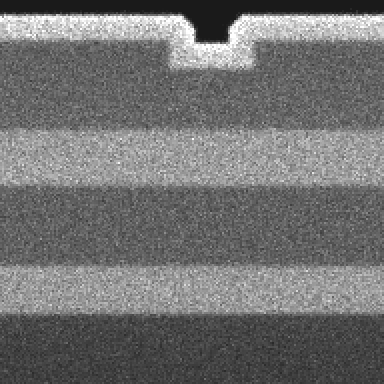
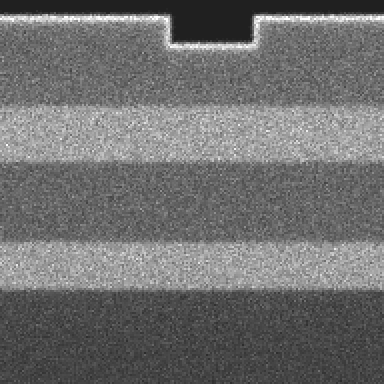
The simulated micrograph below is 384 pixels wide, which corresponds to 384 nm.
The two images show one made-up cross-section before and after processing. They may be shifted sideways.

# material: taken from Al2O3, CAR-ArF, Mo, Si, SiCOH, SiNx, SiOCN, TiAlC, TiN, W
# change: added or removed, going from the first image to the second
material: W
change: removed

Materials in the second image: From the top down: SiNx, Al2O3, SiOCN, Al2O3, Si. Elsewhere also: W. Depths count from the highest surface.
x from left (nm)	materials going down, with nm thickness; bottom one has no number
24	SiNx 90, Al2O3 56, SiOCN 80, Al2O3 48, Si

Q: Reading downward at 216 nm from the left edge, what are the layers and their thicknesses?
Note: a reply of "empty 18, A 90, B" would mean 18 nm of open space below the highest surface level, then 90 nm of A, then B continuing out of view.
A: empty 28, SiNx 62, Al2O3 56, SiOCN 80, Al2O3 48, Si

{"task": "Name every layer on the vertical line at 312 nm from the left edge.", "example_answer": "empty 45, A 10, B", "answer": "SiNx 90, Al2O3 56, SiOCN 80, Al2O3 48, Si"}